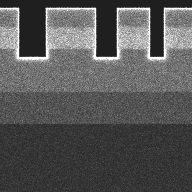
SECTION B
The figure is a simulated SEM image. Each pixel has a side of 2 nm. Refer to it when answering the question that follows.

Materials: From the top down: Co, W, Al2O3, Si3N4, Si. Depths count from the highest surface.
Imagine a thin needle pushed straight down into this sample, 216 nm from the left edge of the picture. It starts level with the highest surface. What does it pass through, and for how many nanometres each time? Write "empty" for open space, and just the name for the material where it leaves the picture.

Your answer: empty 98, Al2O3 70, Si3N4 64, Si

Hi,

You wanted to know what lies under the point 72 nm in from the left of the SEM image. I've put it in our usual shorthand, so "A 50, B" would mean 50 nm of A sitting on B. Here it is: empty 98, Al2O3 70, Si3N4 64, Si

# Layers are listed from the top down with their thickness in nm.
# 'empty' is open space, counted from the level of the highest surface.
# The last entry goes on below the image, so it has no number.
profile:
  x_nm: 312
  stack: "empty 98, Al2O3 70, Si3N4 64, Si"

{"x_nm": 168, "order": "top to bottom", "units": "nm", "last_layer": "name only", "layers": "Co 38, W 44, Al2O3 86, Si3N4 64, Si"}